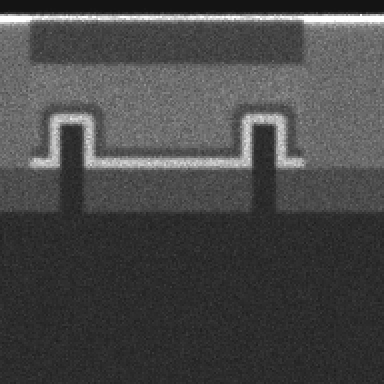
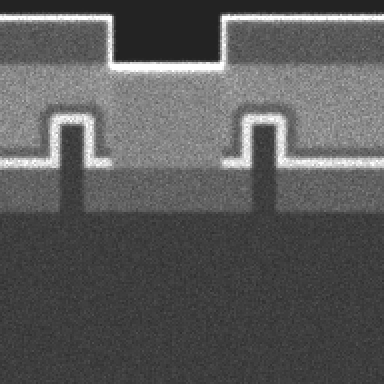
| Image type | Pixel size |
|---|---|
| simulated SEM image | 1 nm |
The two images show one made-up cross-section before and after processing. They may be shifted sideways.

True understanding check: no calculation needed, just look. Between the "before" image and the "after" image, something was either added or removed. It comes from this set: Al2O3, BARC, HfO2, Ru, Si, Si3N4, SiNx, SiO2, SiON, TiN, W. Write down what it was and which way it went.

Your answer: Al2O3 (removed)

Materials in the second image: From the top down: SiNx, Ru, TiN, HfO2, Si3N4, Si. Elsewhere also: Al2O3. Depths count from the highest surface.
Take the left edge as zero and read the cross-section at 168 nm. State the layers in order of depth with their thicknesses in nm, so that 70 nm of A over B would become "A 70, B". empty 48, Al2O3 104, Si3N4 44, Si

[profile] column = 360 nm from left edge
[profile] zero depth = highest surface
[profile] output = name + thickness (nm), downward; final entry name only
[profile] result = SiNx 48, Ru 84, TiN 10, HfO2 10, Si3N4 44, Si